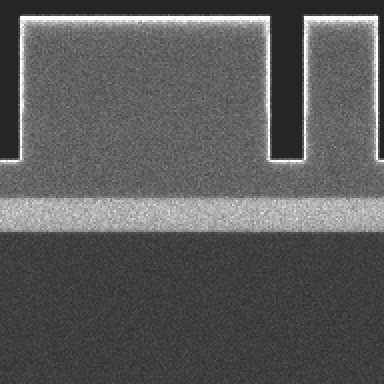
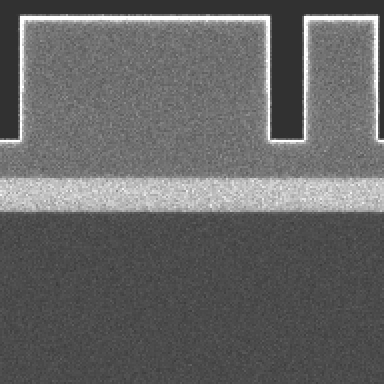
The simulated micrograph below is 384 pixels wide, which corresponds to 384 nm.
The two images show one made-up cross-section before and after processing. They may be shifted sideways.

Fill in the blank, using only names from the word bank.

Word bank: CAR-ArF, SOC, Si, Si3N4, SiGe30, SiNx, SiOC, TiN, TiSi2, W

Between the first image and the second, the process removed SOC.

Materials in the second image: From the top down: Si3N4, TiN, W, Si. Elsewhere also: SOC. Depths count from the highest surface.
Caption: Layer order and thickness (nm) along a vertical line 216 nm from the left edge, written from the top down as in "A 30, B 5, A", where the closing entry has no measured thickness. Si3N4 76, TiN 86, W 34, Si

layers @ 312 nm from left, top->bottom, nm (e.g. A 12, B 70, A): Si3N4 76, TiN 86, W 34, Si